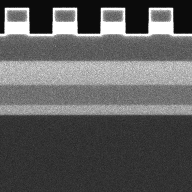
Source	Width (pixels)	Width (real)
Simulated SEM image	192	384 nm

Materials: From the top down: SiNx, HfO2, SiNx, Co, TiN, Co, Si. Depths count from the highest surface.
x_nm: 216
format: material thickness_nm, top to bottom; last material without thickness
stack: SiNx 28, HfO2 24, SiNx 54, Co 48, TiN 40, Co 20, Si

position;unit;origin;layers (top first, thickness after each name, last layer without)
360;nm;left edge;empty 52, SiNx 54, Co 48, TiN 40, Co 20, Si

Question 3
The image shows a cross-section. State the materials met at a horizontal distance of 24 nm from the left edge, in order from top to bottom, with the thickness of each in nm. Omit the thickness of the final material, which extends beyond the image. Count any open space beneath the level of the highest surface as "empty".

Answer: SiNx 28, HfO2 24, SiNx 54, Co 48, TiN 40, Co 20, Si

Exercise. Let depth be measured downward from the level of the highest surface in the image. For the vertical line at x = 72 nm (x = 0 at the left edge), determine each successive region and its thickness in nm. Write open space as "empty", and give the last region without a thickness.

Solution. empty 52, SiNx 54, Co 48, TiN 40, Co 20, Si